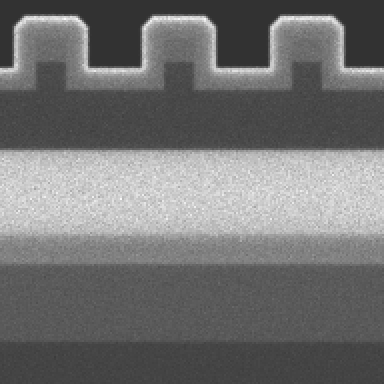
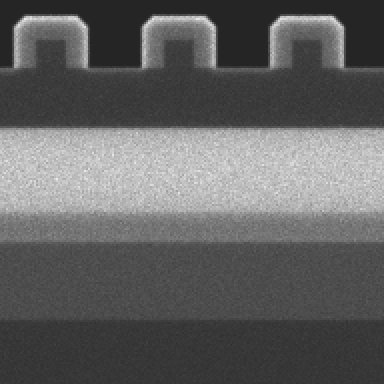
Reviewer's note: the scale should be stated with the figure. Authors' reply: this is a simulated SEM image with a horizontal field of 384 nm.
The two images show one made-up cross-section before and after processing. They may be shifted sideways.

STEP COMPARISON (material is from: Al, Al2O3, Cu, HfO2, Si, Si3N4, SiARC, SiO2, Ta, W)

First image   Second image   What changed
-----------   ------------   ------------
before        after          Al2O3, removed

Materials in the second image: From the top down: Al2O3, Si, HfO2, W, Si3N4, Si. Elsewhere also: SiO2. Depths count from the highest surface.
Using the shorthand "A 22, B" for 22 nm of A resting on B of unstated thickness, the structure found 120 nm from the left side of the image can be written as empty 52, Si 60, HfO2 84, W 30, Si3N4 78, Si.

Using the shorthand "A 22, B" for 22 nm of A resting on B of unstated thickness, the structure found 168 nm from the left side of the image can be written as SiO2 24, Si 88, HfO2 84, W 30, Si3N4 78, Si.